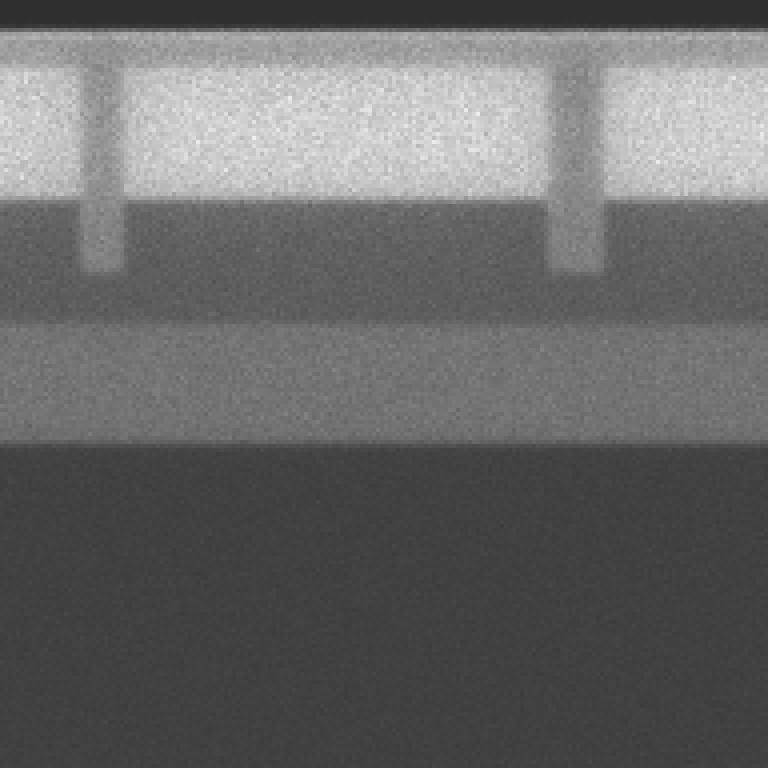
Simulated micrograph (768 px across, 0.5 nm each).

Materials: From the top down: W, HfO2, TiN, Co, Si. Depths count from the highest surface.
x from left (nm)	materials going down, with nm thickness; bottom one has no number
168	W 18, HfO2 66, TiN 62, Co 60, Si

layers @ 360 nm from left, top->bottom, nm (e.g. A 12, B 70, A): W 18, HfO2 66, TiN 62, Co 60, Si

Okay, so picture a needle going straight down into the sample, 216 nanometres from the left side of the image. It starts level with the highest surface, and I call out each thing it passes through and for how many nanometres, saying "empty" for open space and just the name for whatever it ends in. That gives W 18, HfO2 66, TiN 62, Co 60, Si